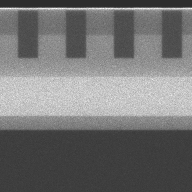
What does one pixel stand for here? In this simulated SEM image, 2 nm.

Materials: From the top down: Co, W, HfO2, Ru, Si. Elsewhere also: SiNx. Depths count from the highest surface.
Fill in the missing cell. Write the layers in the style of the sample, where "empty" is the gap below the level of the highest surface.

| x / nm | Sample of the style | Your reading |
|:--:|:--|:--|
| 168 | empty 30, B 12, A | SiNx 100, W 38, HfO2 78, Ru 28, Si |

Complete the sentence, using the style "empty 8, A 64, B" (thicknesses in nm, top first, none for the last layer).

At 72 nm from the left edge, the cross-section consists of SiNx 100, W 38, HfO2 78, Ru 28, Si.